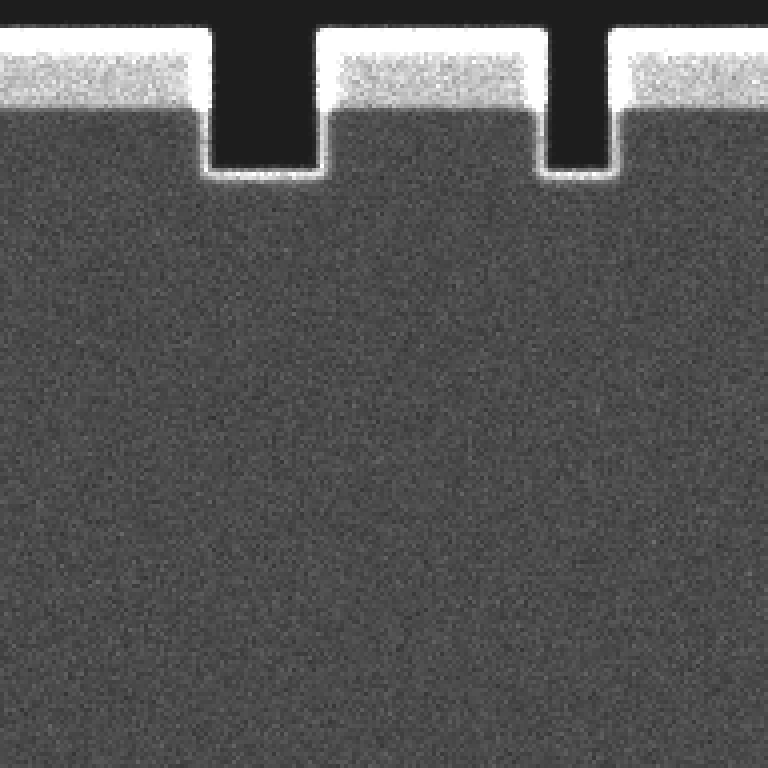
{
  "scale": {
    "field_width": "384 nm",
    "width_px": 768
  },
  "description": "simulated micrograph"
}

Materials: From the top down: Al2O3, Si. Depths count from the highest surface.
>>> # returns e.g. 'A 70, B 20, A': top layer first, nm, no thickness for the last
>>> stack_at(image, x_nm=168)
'Al2O3 38, Si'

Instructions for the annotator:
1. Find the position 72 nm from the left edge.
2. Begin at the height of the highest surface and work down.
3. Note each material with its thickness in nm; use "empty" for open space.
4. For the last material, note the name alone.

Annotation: Al2O3 38, Si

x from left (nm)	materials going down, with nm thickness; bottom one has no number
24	Al2O3 38, Si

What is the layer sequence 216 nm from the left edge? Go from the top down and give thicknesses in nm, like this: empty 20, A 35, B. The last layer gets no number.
Al2O3 38, Si